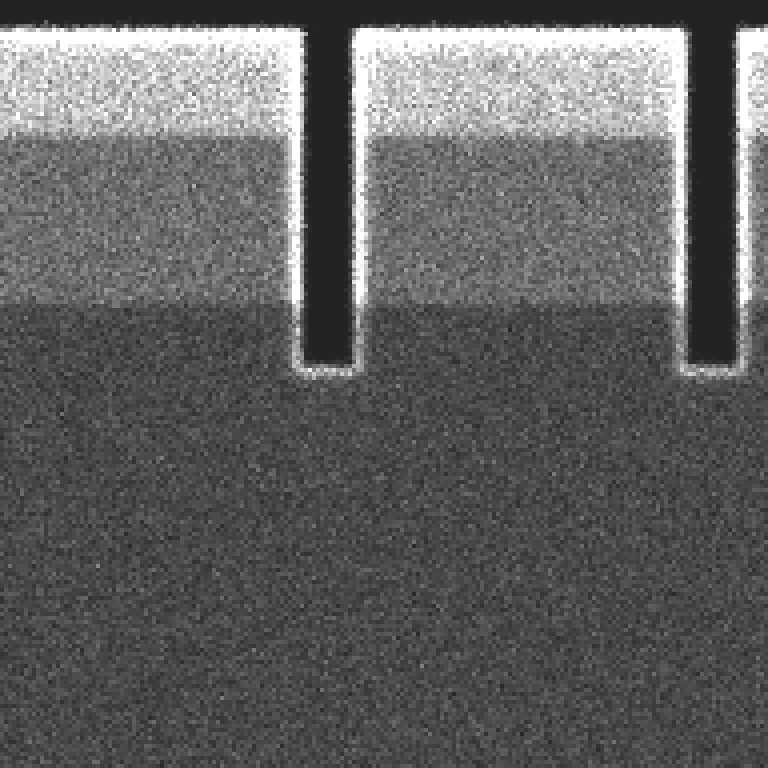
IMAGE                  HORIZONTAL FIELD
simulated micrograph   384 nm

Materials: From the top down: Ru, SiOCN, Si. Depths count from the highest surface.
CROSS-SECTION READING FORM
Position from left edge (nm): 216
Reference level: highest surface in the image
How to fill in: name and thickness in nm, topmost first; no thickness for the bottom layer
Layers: Ru 52, SiOCN 84, Si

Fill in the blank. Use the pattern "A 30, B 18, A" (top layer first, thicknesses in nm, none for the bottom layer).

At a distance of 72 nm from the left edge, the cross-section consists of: Ru 52, SiOCN 84, Si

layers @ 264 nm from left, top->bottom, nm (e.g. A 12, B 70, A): Ru 52, SiOCN 84, Si